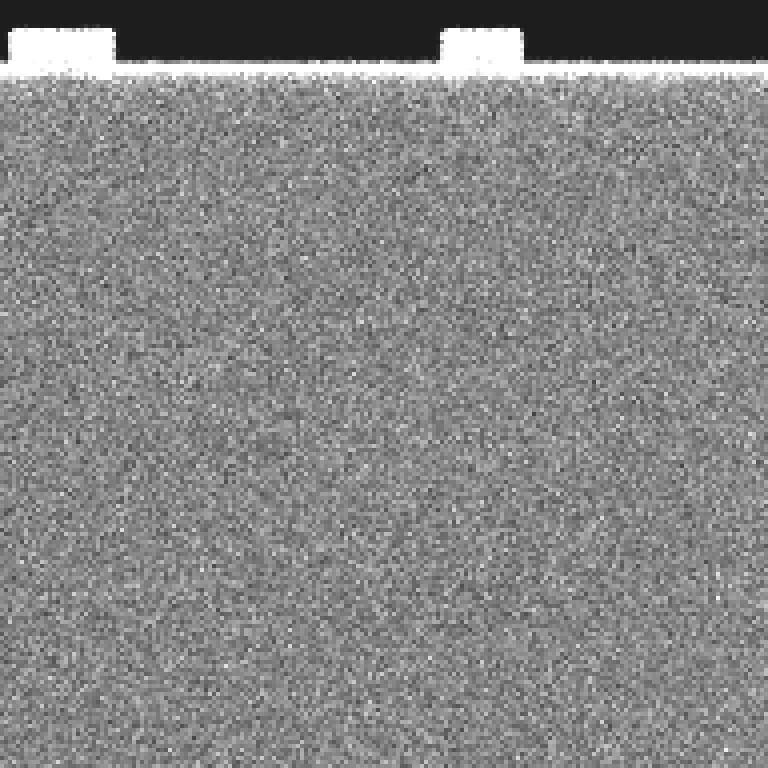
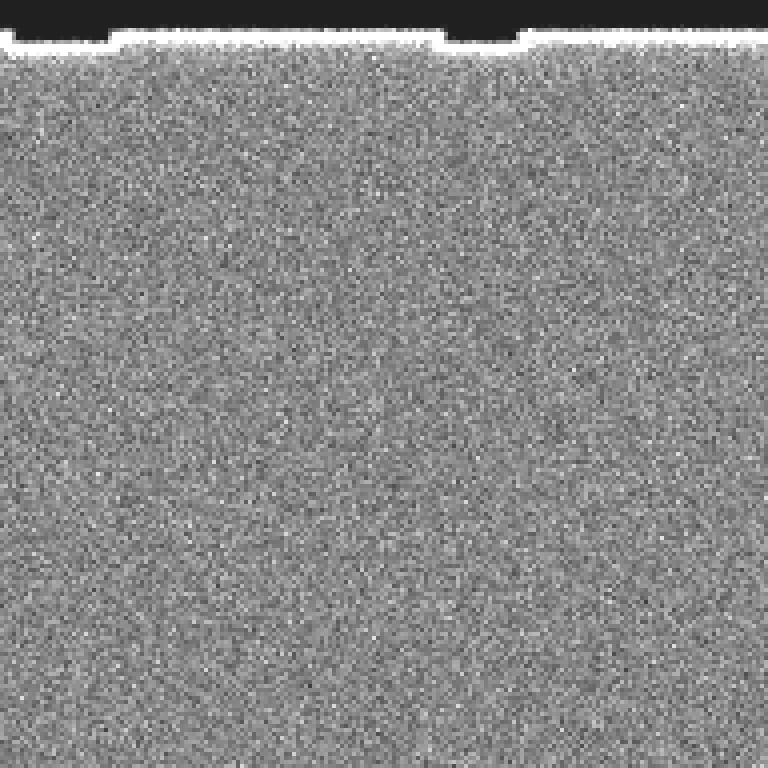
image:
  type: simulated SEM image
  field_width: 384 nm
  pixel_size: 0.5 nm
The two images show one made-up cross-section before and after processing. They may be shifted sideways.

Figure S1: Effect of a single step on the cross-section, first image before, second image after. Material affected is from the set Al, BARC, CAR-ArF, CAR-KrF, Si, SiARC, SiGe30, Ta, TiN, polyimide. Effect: removed SiARC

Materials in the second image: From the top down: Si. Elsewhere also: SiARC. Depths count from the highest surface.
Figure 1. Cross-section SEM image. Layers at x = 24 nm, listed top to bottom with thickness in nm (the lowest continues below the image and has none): empty 6, Si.